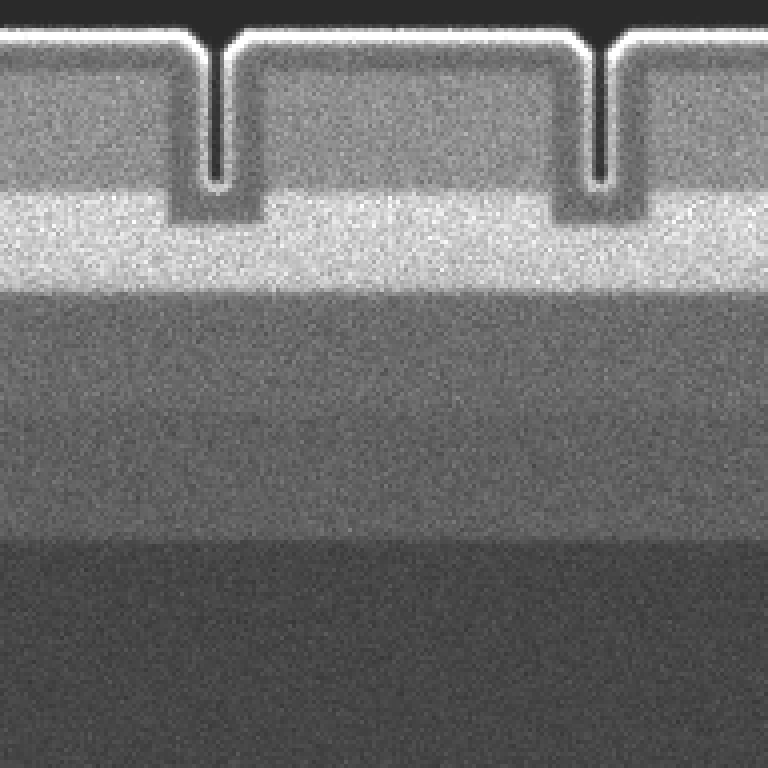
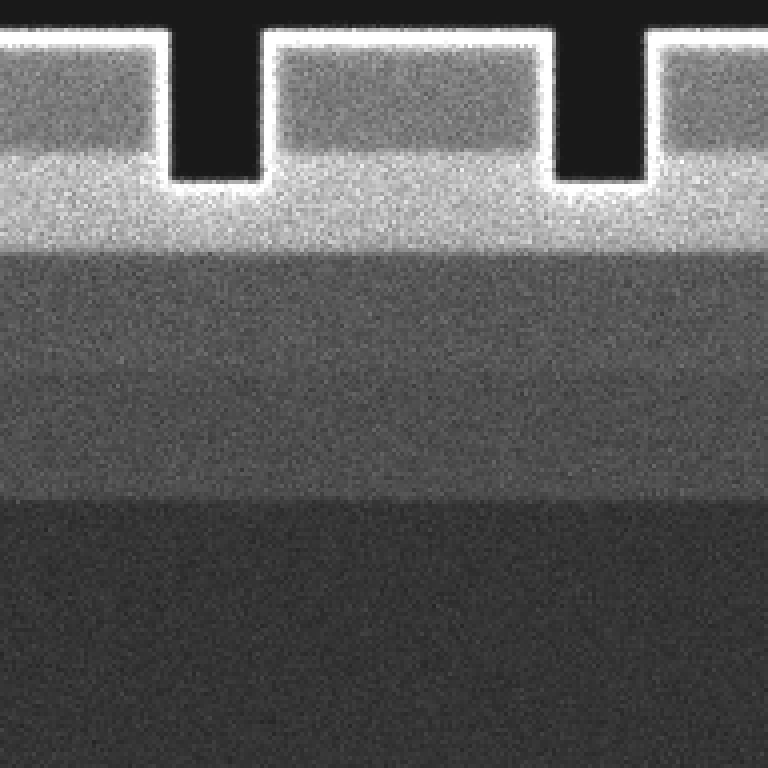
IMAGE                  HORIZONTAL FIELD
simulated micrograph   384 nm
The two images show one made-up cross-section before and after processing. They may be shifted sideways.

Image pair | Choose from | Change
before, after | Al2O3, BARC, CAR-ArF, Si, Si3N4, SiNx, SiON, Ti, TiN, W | Si3N4 (removed)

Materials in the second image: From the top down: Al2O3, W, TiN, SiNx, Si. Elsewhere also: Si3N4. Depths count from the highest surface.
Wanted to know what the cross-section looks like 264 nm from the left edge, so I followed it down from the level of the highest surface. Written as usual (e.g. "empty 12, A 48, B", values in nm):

Al2O3 60, W 50, TiN 60, SiNx 64, Si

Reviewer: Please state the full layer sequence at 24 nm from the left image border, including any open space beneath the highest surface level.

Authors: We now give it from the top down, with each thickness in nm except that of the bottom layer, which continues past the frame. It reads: Al2O3 60, W 50, TiN 60, SiNx 64, Si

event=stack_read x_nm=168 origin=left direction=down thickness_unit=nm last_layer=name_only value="Al2O3 60, W 50, TiN 60, SiNx 64, Si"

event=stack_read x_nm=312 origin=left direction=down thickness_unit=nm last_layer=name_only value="empty 76, W 34, TiN 60, SiNx 64, Si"